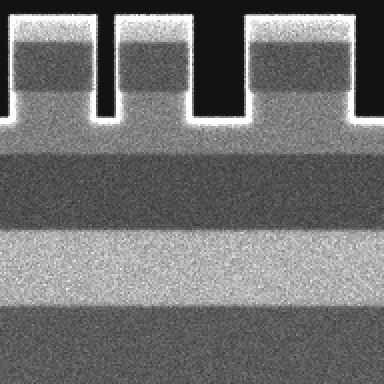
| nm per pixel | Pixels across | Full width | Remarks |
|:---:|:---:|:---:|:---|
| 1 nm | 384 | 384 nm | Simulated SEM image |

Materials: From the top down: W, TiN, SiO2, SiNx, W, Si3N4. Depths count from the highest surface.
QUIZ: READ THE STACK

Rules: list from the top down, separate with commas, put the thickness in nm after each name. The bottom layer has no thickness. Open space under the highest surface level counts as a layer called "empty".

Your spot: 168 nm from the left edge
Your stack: W 26, TiN 50, SiO2 62, SiNx 76, W 76, Si3N4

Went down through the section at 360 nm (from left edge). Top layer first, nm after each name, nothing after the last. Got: empty 102, SiO2 36, SiNx 76, W 76, Si3N4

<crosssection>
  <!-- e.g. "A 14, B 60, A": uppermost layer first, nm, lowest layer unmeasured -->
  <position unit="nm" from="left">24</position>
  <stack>W 26, TiN 50, SiO2 62, SiNx 76, W 76, Si3N4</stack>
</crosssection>